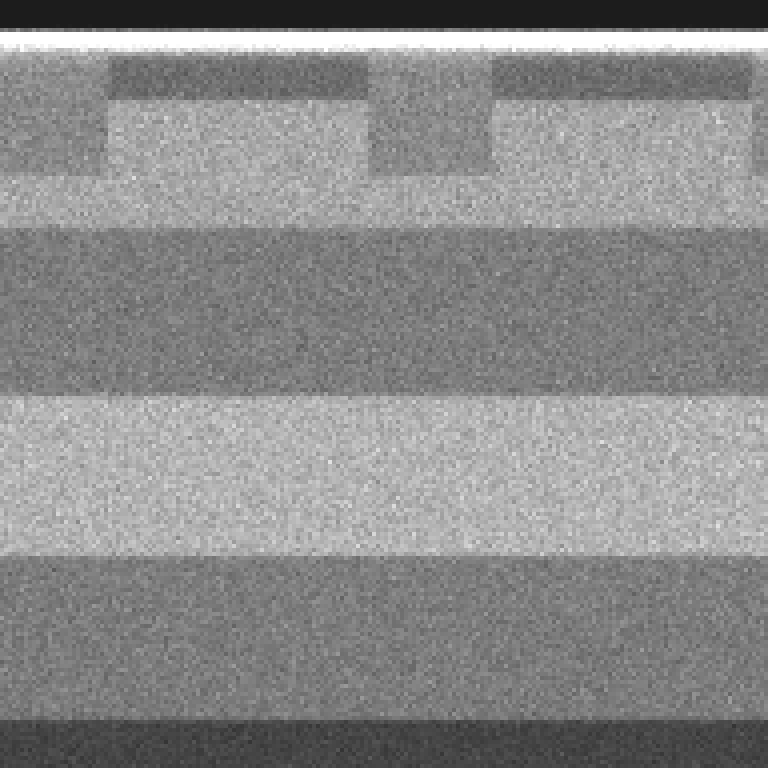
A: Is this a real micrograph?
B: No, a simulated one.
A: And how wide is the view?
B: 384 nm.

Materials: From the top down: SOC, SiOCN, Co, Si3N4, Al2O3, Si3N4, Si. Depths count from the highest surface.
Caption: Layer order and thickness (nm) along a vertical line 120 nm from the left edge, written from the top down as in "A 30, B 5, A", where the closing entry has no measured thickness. SOC 8, SiOCN 26, Co 64, Si3N4 84, Al2O3 80, Si3N4 82, Si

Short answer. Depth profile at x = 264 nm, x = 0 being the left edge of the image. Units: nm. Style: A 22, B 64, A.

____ SOC 8, SiOCN 26, Co 64, Si3N4 84, Al2O3 80, Si3N4 82, Si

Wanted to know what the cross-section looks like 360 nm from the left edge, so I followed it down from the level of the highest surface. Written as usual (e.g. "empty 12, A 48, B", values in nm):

SOC 8, SiOCN 26, Co 64, Si3N4 84, Al2O3 80, Si3N4 82, Si